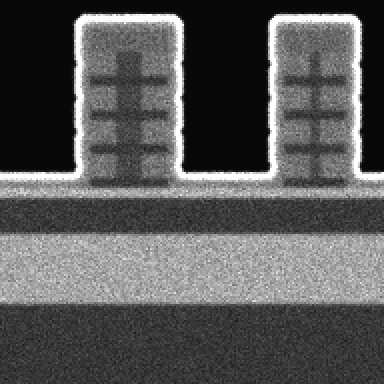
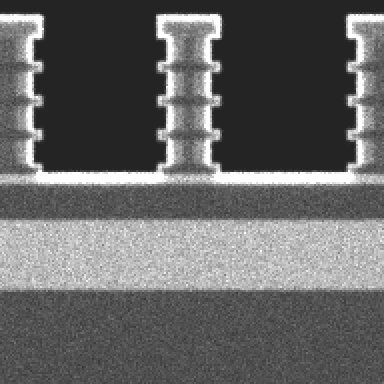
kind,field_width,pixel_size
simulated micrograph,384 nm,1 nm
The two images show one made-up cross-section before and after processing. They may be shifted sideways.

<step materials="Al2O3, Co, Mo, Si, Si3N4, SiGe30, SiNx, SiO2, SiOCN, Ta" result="removed Si3N4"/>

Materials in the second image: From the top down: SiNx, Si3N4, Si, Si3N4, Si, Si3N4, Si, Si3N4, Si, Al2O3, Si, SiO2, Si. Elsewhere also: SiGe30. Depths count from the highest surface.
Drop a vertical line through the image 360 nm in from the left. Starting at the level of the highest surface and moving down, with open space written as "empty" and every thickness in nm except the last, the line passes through SiNx 22, Si3N4 24, Si 10, Si3N4 24, Si 10, Si3N4 24, Si 10, Si3N4 24, Si 10, Al2O3 10, Si 36, SiO2 70, Si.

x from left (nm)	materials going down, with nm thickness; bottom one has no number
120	empty 158, Al2O3 10, Si 36, SiO2 70, Si